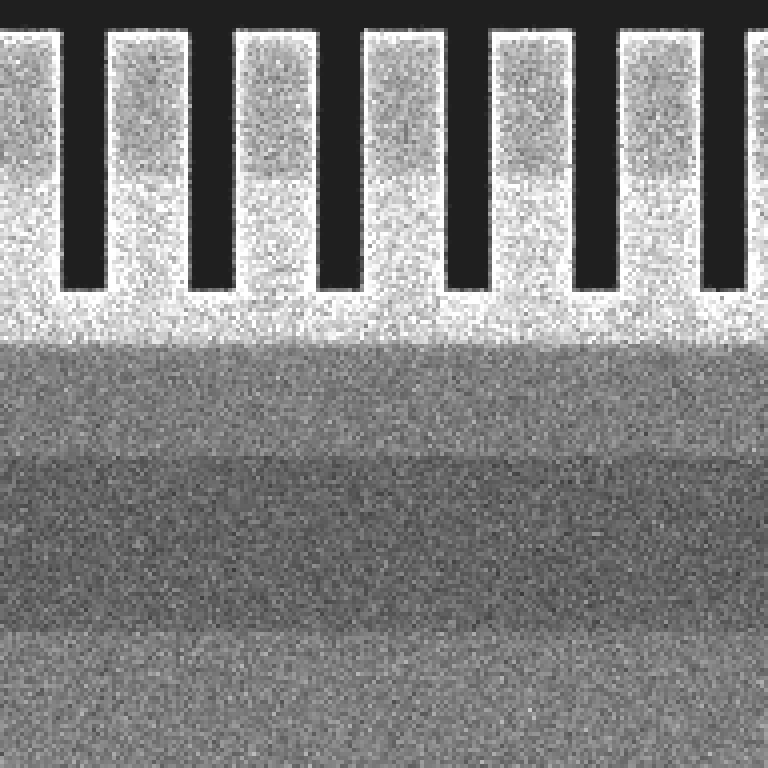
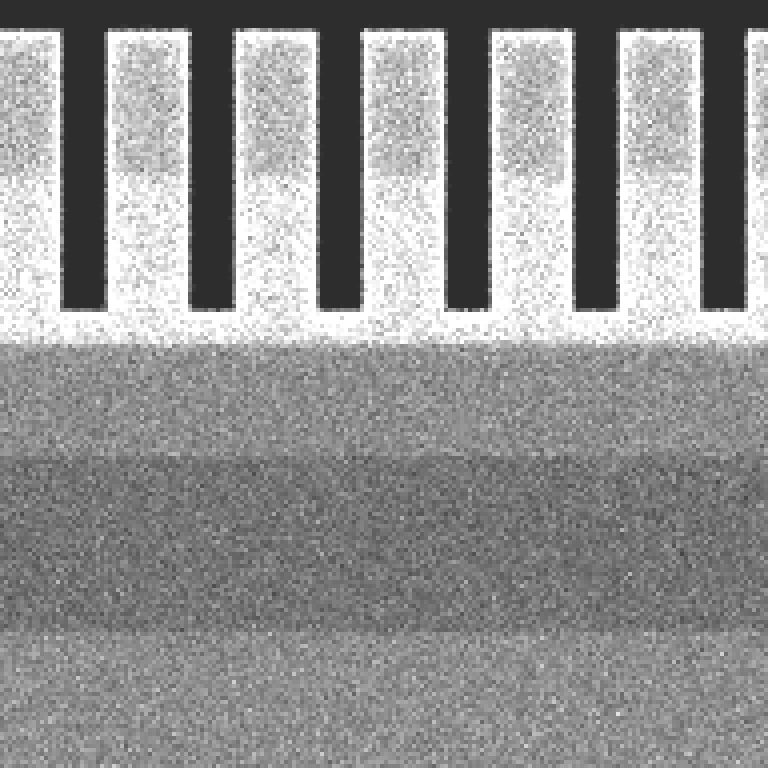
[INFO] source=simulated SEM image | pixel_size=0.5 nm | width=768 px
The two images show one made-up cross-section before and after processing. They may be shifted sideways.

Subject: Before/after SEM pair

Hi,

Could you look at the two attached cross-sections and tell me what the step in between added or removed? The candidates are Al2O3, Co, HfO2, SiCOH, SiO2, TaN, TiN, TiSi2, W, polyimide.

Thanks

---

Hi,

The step removed W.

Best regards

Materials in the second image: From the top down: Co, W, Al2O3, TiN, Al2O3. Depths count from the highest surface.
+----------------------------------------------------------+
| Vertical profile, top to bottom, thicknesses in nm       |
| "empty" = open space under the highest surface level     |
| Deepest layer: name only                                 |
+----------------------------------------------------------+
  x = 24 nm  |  Co 72, W 84, Al2O3 56, TiN 88, Al2O3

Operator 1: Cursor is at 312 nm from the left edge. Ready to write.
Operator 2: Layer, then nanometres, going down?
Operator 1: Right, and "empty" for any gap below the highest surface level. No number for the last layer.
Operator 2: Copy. Co 72, W 84, Al2O3 56, TiN 88, Al2O3